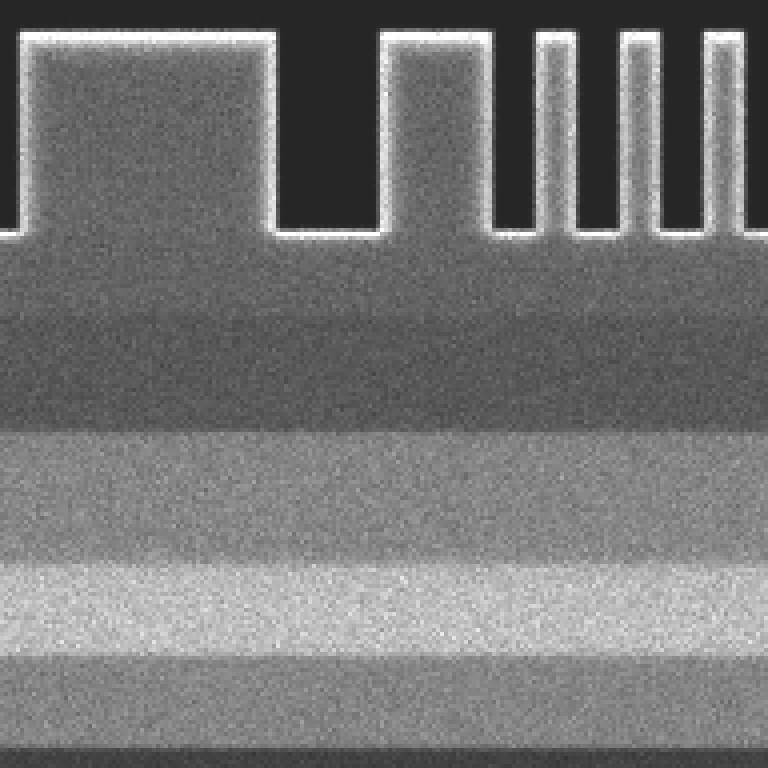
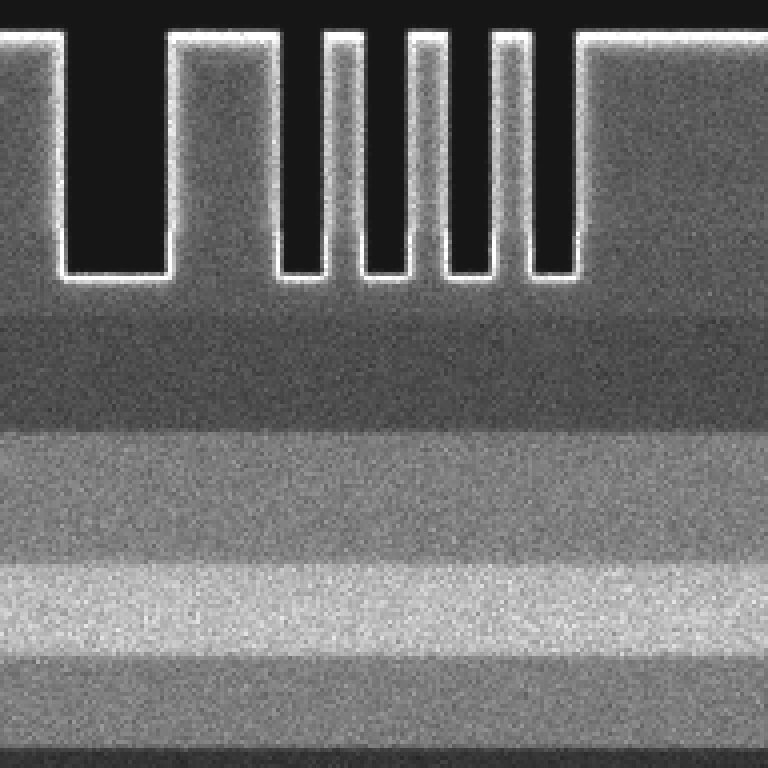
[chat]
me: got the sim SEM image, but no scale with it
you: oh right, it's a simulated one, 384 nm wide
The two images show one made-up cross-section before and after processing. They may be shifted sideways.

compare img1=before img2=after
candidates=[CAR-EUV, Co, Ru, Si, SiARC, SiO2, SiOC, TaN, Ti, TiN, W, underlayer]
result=removed:TiN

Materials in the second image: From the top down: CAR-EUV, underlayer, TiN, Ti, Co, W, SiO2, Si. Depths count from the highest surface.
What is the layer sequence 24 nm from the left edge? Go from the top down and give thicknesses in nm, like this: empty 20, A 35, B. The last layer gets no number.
CAR-EUV 74, underlayer 26, TiN 42, Ti 58, Co 66, W 46, SiO2 46, Si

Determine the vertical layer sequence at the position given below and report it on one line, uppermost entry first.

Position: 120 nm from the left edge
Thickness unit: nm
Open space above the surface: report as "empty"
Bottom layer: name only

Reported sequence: CAR-EUV 74, underlayer 26, TiN 42, Ti 58, Co 66, W 46, SiO2 46, Si